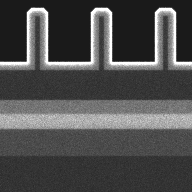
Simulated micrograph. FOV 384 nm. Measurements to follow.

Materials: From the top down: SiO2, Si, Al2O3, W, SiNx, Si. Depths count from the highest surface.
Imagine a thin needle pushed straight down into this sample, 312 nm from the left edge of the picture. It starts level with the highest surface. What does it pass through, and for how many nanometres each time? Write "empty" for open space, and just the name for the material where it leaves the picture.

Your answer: empty 6, SiO2 118, Si 60, Al2O3 28, W 30, SiNx 54, Si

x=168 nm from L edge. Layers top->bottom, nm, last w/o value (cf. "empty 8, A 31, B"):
empty 108, SiO2 16, Si 60, Al2O3 28, W 30, SiNx 54, Si